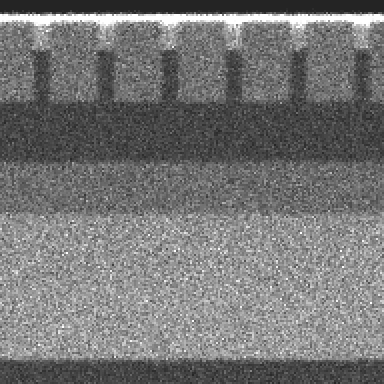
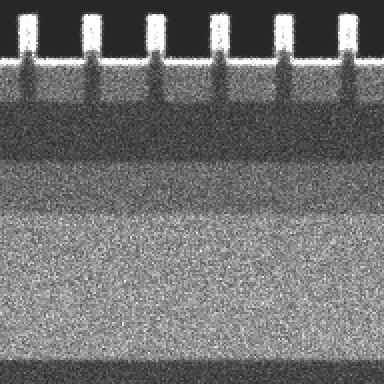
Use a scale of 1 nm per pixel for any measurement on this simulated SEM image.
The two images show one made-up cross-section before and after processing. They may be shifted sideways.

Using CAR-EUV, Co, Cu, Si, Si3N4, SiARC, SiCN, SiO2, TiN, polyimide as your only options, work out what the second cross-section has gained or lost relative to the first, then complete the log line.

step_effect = removed Si3N4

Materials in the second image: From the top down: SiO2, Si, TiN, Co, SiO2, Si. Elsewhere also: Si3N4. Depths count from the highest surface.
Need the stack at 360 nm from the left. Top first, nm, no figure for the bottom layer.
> empty 44, Si3N4 42, Si 60, TiN 52, Co 72, SiO2 74, Si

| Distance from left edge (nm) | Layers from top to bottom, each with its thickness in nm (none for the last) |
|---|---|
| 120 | empty 44, Si3N4 42, Si 60, TiN 52, Co 72, SiO2 74, Si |